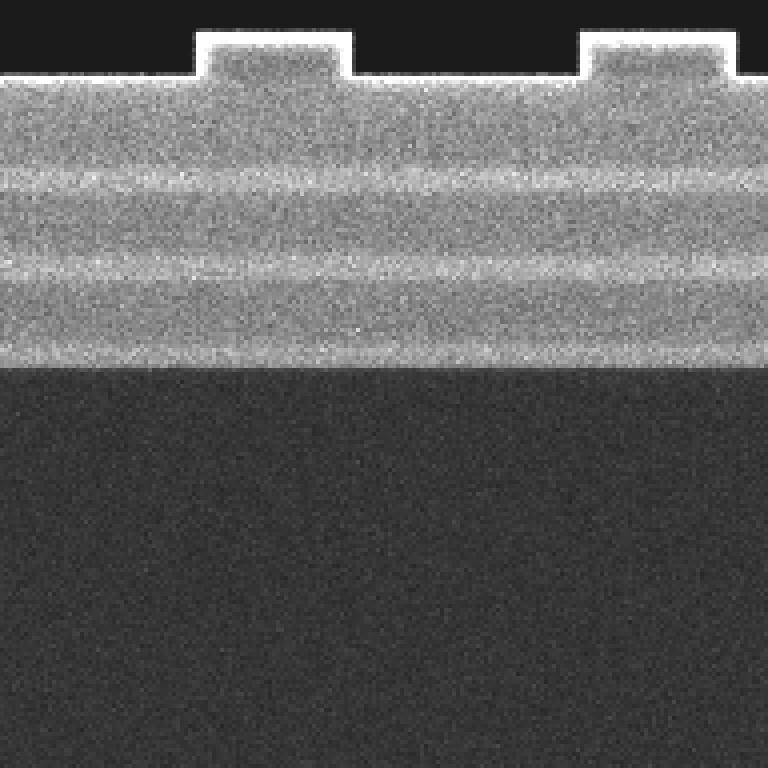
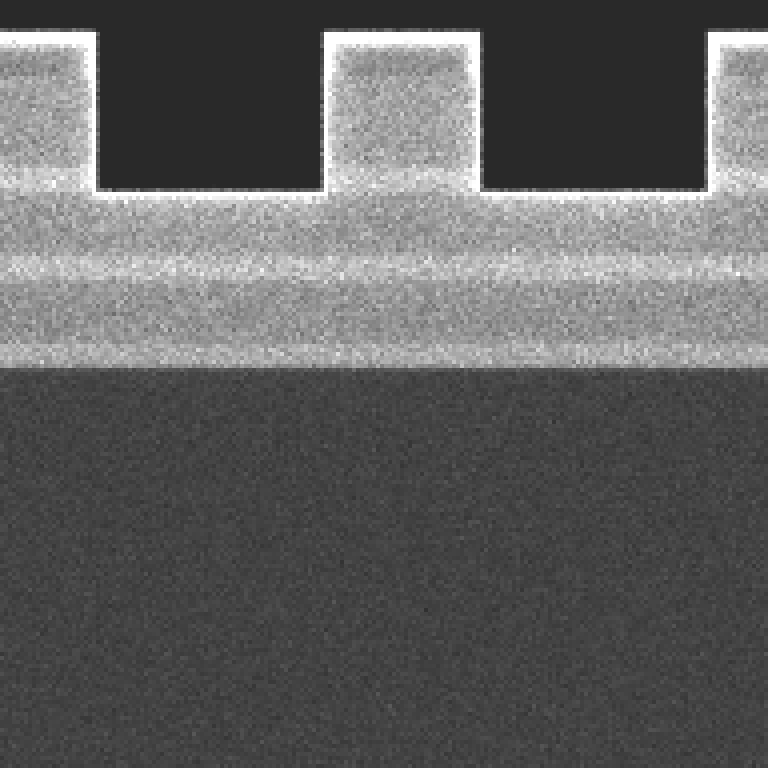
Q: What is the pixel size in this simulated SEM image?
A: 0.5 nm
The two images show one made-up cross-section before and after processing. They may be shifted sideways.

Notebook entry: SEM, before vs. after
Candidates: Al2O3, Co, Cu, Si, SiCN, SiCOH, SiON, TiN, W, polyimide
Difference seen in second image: Co and W removed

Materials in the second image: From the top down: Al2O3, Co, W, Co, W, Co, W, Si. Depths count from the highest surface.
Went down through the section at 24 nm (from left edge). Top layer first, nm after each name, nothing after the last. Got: Al2O3 22, Co 46, W 12, Co 32, W 12, Co 32, W 12, Si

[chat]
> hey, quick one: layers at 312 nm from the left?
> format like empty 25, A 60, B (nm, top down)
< empty 80, Co 32, W 12, Co 32, W 12, Si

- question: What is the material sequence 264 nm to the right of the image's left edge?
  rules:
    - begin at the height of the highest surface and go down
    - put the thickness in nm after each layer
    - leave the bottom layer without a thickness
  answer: empty 80, Co 32, W 12, Co 32, W 12, Si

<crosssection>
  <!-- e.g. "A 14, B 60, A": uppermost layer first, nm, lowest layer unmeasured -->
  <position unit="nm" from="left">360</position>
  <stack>Al2O3 22, Co 46, W 12, Co 32, W 12, Co 32, W 12, Si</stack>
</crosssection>